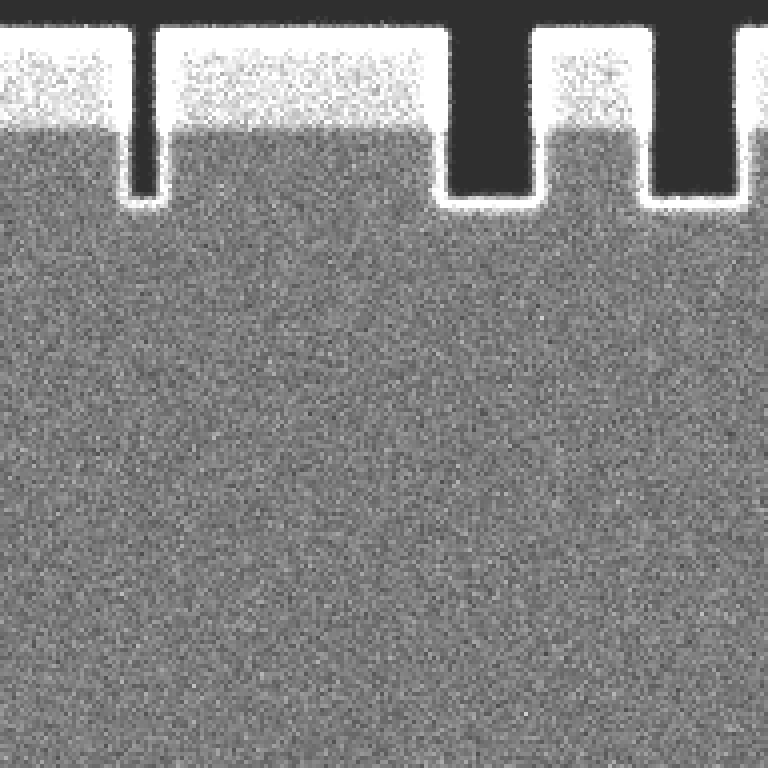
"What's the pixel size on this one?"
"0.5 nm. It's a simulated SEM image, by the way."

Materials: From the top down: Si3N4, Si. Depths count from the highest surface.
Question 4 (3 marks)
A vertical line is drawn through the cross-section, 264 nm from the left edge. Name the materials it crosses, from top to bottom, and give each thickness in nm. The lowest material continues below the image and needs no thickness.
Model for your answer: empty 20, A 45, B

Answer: empty 84, Si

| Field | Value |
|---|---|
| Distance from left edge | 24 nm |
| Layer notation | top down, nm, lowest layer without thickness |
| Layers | Si3N4 48, Si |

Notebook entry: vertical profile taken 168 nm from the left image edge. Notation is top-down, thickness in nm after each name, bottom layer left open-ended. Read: Si3N4 48, Si